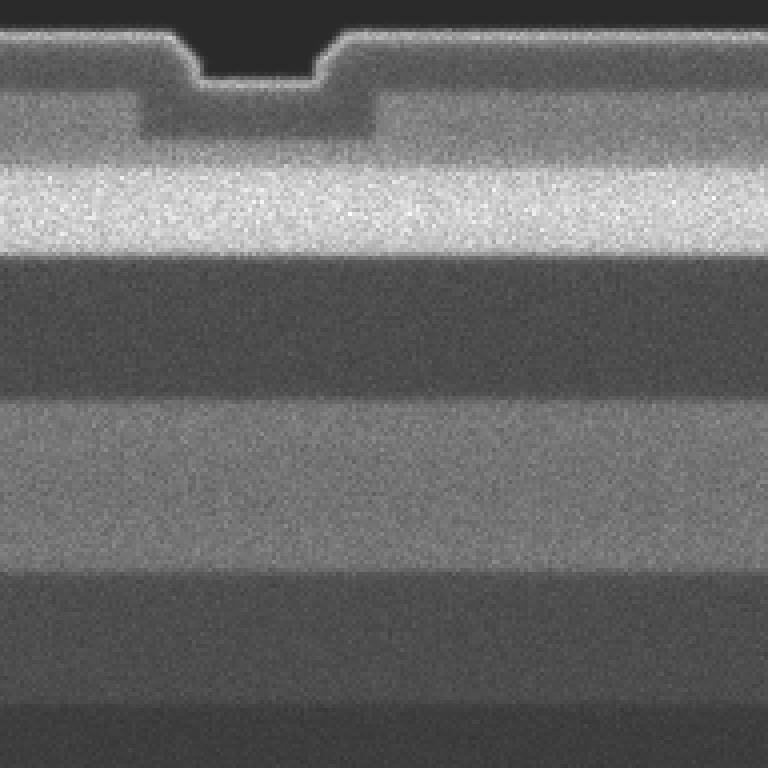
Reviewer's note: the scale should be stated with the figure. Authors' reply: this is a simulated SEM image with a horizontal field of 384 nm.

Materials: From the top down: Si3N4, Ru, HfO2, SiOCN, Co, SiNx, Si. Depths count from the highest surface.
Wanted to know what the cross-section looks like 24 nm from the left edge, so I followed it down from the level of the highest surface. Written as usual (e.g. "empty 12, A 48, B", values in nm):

Si3N4 30, Ru 38, HfO2 44, SiOCN 72, Co 86, SiNx 66, Si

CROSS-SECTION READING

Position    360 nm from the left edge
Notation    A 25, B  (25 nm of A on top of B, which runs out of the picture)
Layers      Si3N4 30, Ru 38, HfO2 44, SiOCN 72, Co 86, SiNx 66, Si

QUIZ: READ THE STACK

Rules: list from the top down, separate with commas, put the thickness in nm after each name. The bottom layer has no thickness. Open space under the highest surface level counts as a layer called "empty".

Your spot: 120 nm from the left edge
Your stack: empty 24, Si3N4 30, Ru 14, HfO2 44, SiOCN 72, Co 86, SiNx 66, Si